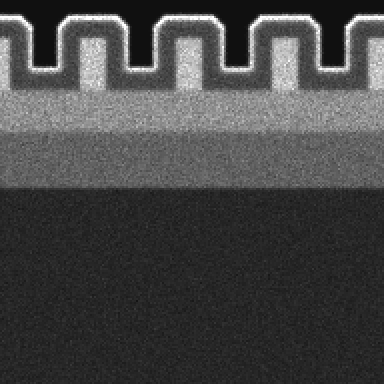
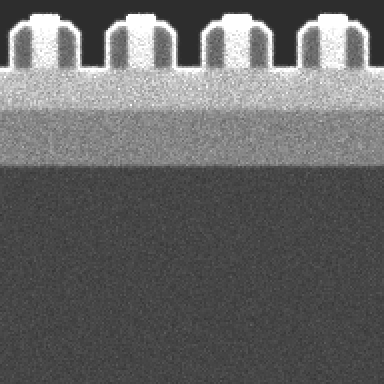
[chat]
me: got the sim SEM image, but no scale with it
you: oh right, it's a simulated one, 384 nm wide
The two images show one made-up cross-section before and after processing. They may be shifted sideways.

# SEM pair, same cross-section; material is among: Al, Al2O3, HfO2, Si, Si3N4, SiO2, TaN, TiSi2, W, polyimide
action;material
removed;Si3N4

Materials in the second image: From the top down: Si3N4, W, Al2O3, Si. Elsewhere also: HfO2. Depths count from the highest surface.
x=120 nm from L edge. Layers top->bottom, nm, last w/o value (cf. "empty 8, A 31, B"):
empty 6, Si3N4 46, W 42, Al2O3 56, Si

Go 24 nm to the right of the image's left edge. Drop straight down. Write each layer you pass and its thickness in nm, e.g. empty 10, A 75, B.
empty 6, Si3N4 46, W 42, Al2O3 56, Si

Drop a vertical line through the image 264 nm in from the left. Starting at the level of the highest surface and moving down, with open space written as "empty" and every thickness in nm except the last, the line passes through empty 10, Si3N4 42, W 42, Al2O3 56, Si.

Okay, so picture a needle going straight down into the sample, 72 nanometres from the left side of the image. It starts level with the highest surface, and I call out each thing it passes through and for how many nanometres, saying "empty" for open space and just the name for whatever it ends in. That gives empty 10, Si3N4 42, W 42, Al2O3 56, Si